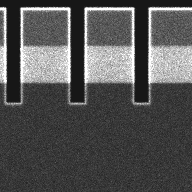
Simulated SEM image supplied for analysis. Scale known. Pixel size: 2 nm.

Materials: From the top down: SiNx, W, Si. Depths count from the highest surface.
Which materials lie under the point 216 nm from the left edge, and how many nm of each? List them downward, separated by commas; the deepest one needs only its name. SiNx 76, W 74, Si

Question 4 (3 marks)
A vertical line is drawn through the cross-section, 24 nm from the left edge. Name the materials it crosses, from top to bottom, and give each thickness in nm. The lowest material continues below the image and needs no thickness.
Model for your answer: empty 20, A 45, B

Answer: empty 190, Si